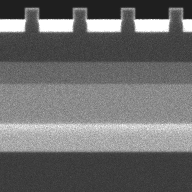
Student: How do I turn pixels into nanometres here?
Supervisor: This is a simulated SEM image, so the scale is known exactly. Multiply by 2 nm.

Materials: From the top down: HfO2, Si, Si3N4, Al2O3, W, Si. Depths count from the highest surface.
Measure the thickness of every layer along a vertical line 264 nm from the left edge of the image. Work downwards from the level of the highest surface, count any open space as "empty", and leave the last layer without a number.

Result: Si 108, Si3N4 44, Al2O3 80, W 56, Si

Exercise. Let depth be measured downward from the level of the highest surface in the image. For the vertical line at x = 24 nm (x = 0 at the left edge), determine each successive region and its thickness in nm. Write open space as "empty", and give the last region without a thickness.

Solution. empty 24, HfO2 24, Si 60, Si3N4 44, Al2O3 80, W 56, Si